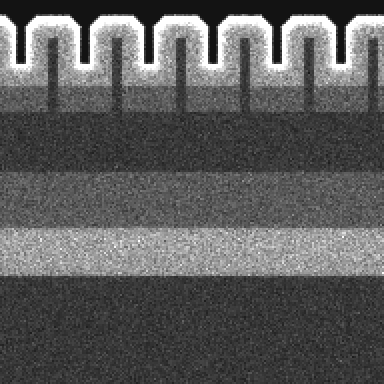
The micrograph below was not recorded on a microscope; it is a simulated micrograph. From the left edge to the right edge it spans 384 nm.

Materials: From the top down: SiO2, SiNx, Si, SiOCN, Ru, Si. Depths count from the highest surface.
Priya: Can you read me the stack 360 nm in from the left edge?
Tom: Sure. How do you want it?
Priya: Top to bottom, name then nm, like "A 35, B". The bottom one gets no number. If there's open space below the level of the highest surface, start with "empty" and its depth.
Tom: SiO2 70, SiNx 26, Si 60, SiOCN 56, Ru 48, Si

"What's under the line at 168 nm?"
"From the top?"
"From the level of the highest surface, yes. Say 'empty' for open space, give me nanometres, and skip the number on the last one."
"SiO2 70, SiNx 26, Si 60, SiOCN 56, Ru 48, Si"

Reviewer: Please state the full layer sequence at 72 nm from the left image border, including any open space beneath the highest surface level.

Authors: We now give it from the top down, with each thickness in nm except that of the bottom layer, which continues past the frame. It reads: empty 4, SiO2 66, SiNx 26, Si 60, SiOCN 56, Ru 48, Si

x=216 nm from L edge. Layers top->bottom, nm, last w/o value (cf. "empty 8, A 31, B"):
empty 48, SiO2 22, SiNx 26, Si 60, SiOCN 56, Ru 48, Si